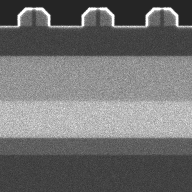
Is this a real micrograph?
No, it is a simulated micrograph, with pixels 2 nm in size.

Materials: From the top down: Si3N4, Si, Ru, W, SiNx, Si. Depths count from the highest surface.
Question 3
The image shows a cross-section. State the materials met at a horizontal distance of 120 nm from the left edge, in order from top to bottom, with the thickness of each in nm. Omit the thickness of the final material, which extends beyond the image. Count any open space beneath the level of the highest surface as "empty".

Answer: empty 36, Si 60, Ru 90, W 74, SiNx 34, Si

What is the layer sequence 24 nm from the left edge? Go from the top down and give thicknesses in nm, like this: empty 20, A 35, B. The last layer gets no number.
empty 36, Si 60, Ru 90, W 74, SiNx 34, Si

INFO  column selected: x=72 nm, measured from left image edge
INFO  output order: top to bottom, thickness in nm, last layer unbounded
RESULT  Si3N4 36, Si 60, Ru 90, W 74, SiNx 34, Si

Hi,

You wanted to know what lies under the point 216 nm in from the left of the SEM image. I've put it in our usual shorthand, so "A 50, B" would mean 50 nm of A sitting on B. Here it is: empty 4, Si3N4 32, Si 60, Ru 90, W 74, SiNx 34, Si